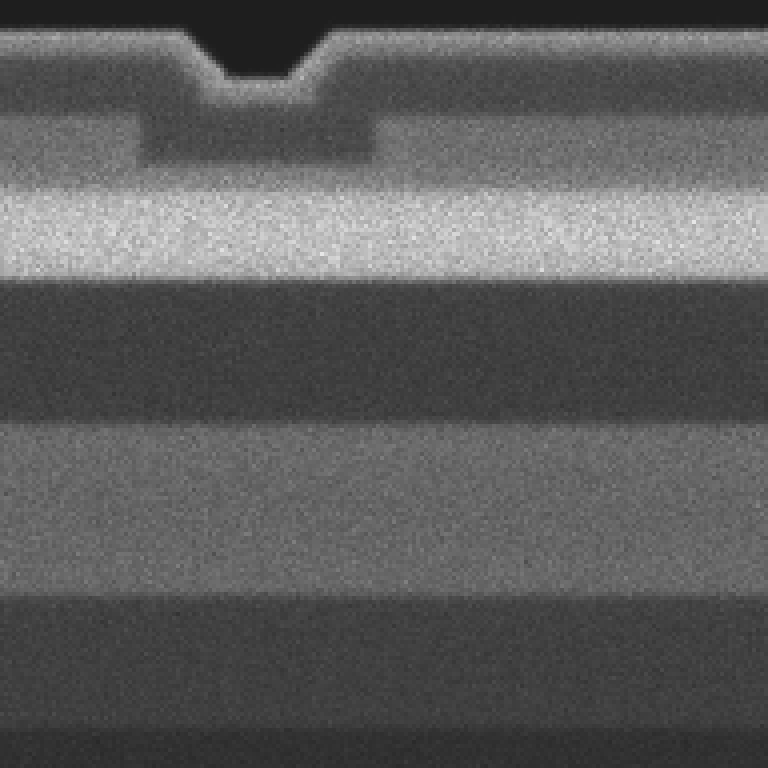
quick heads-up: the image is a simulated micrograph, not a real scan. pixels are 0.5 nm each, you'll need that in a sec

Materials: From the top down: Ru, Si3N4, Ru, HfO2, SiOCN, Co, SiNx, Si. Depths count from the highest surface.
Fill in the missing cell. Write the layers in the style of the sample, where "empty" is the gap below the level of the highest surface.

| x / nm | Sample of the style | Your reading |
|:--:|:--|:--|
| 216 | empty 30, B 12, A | Ru 12, Si3N4 30, Ru 38, HfO2 44, SiOCN 72, Co 86, SiNx 66, Si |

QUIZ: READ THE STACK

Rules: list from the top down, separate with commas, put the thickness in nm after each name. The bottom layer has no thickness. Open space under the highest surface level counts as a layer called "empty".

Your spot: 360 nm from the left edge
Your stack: Ru 12, Si3N4 30, Ru 38, HfO2 44, SiOCN 72, Co 86, SiNx 66, Si